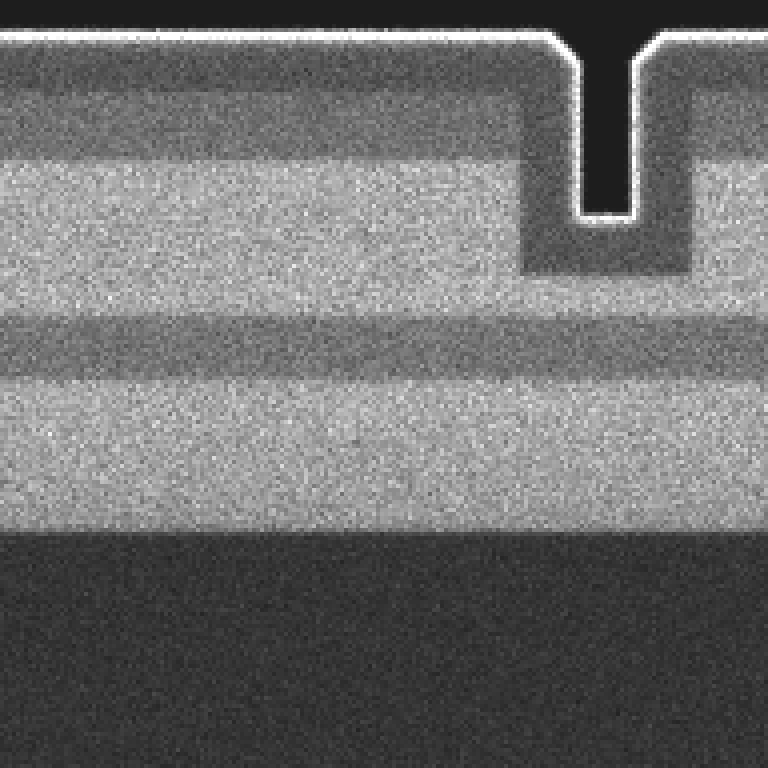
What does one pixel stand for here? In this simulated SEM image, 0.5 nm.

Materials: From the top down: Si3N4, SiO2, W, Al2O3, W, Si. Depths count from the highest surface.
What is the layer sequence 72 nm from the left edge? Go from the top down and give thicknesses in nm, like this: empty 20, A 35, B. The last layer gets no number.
Si3N4 30, SiO2 34, W 78, Al2O3 32, W 76, Si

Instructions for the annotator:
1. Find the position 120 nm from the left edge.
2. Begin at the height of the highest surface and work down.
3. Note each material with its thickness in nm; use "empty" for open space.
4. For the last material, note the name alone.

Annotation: Si3N4 30, SiO2 34, W 78, Al2O3 32, W 76, Si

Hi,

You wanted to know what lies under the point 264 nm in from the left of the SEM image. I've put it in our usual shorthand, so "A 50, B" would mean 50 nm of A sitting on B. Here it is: Si3N4 122, W 20, Al2O3 32, W 76, Si